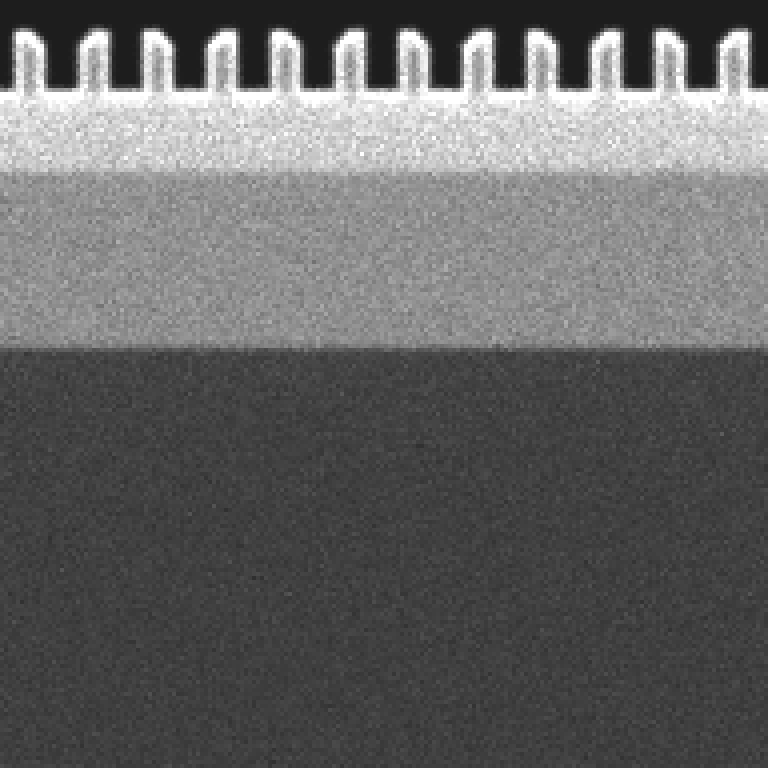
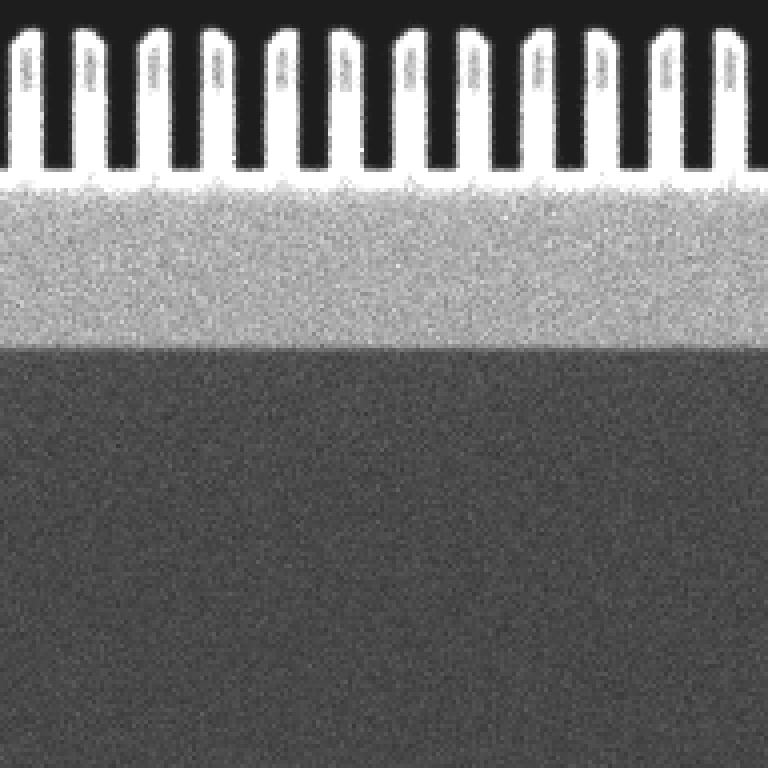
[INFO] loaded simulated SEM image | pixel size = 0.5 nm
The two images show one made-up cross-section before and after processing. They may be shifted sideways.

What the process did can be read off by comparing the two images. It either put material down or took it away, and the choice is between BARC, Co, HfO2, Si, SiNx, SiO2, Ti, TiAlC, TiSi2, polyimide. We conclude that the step removed Co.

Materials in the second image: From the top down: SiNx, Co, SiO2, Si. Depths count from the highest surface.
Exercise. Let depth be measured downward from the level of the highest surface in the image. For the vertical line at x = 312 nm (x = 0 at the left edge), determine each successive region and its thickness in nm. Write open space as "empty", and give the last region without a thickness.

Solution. empty 70, SiO2 88, Si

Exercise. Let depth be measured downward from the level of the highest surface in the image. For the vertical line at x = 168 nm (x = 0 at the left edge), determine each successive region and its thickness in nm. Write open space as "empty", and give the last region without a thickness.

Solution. SiNx 30, Co 40, SiO2 88, Si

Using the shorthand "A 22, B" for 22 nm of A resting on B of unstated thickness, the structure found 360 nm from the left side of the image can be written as SiNx 30, Co 40, SiO2 88, Si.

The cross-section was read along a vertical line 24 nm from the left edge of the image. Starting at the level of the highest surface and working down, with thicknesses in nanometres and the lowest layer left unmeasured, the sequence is empty 70, SiO2 88, Si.